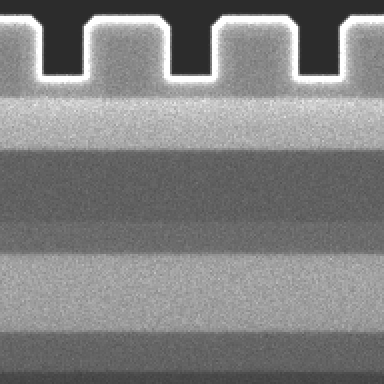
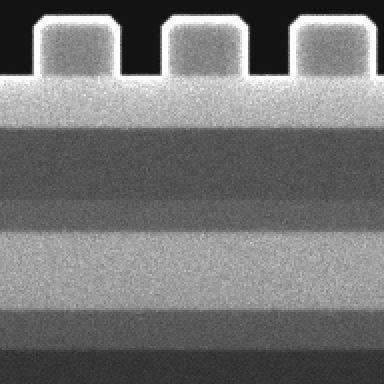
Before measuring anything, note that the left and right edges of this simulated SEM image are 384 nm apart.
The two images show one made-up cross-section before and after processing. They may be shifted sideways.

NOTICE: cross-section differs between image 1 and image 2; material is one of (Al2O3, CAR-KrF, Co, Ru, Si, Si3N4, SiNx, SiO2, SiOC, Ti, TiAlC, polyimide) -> removed: Al2O3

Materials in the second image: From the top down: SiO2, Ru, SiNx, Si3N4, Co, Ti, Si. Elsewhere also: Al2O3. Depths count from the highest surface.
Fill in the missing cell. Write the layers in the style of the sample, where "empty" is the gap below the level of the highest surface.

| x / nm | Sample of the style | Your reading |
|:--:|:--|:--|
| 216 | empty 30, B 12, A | SiO2 60, Ru 52, SiNx 72, Si3N4 32, Co 78, Ti 40, Si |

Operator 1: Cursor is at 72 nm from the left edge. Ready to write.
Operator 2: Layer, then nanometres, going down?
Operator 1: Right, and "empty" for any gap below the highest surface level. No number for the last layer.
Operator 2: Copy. SiO2 60, Ru 52, SiNx 72, Si3N4 32, Co 78, Ti 40, Si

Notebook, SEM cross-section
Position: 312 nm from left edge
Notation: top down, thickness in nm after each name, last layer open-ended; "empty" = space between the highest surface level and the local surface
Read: SiO2 60, Ru 52, SiNx 72, Si3N4 32, Co 78, Ti 40, Si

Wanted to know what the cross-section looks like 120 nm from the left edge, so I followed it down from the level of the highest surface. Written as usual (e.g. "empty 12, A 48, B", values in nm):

empty 60, Ru 52, SiNx 72, Si3N4 32, Co 78, Ti 40, Si